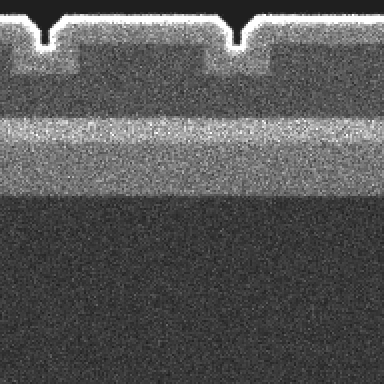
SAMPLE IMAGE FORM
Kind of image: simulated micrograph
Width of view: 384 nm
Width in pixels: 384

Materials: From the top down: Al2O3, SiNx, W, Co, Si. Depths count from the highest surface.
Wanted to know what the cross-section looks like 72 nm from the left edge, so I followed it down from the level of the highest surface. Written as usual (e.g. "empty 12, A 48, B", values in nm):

Al2O3 58, SiNx 44, W 24, Co 54, Si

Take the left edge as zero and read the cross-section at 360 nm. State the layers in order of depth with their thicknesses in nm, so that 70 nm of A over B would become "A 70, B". Al2O3 28, SiNx 74, W 24, Co 54, Si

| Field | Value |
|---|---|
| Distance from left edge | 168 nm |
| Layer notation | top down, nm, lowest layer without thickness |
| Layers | Al2O3 28, SiNx 74, W 24, Co 54, Si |